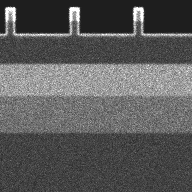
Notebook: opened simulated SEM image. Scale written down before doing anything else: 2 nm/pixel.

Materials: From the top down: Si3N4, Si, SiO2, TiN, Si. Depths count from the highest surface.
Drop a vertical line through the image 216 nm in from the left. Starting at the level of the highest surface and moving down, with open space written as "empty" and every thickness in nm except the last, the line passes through empty 52, Si 60, SiO2 64, TiN 74, Si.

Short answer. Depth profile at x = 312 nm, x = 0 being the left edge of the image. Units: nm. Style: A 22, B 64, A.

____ empty 52, Si 60, SiO2 64, TiN 74, Si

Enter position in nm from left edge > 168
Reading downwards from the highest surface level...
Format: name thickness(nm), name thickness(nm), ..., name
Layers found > empty 52, Si 60, SiO2 64, TiN 74, Si